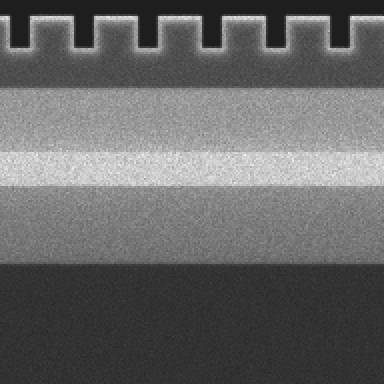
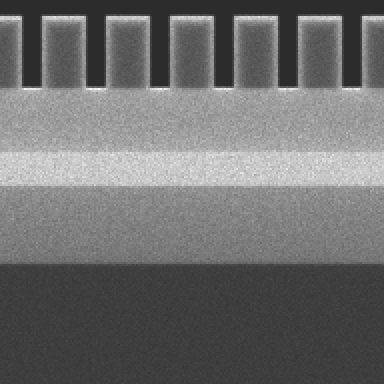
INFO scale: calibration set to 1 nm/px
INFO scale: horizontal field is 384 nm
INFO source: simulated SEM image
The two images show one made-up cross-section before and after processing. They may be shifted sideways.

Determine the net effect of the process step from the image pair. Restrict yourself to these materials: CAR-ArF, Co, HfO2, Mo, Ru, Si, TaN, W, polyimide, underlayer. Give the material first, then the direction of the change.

underlayer: removed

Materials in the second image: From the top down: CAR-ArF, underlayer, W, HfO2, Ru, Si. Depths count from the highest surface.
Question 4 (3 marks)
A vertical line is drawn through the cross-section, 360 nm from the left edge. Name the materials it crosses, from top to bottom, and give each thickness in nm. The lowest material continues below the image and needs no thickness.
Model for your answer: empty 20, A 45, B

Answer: empty 72, W 64, HfO2 34, Ru 78, Si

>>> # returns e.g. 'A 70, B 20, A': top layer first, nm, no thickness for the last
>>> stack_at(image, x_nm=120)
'CAR-ArF 32, underlayer 40, W 64, HfO2 34, Ru 78, Si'